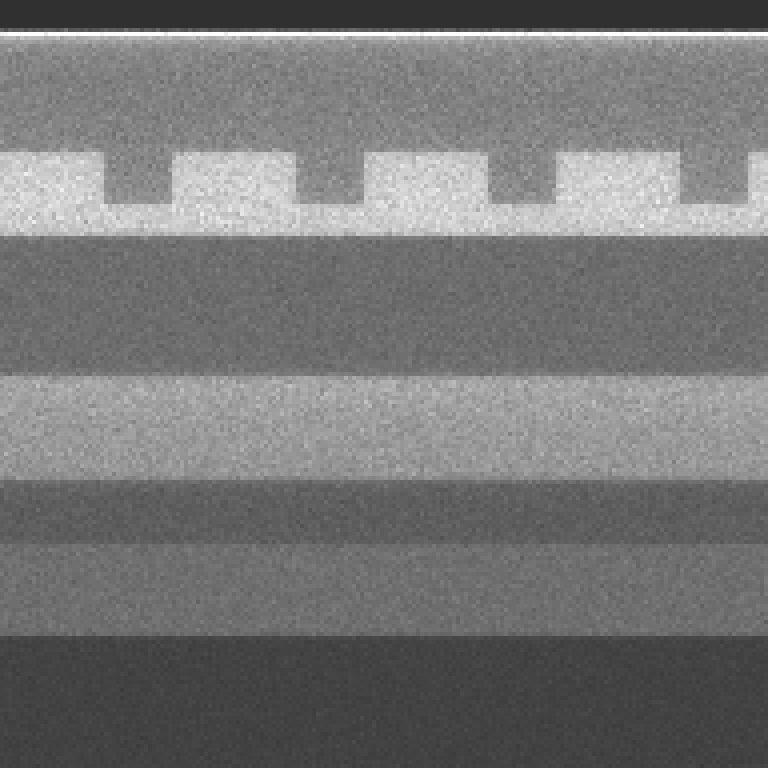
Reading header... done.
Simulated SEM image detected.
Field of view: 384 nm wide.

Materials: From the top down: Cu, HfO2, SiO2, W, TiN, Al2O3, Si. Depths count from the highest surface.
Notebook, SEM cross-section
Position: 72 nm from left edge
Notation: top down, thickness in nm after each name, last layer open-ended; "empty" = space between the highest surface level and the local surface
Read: Cu 86, HfO2 16, SiO2 70, W 52, TiN 32, Al2O3 46, Si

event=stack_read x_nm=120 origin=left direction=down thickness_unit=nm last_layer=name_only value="Cu 60, HfO2 42, SiO2 70, W 52, TiN 32, Al2O3 46, Si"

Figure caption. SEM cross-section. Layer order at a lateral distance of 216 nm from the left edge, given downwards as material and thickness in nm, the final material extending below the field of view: Cu 60, HfO2 42, SiO2 70, W 52, TiN 32, Al2O3 46, Si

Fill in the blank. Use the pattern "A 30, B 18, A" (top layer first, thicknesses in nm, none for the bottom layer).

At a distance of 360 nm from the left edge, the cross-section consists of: Cu 86, HfO2 16, SiO2 70, W 52, TiN 32, Al2O3 46, Si